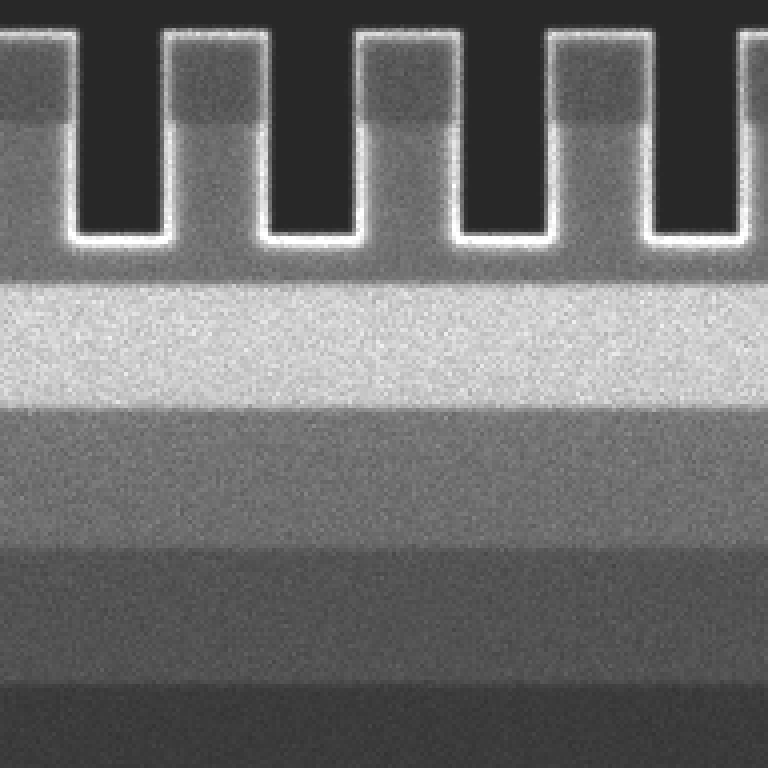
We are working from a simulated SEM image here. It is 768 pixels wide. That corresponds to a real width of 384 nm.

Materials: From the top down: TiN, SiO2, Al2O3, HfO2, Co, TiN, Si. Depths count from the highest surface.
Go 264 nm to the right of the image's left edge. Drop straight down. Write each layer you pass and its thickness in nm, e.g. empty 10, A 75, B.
empty 102, Al2O3 24, HfO2 62, Co 70, TiN 68, Si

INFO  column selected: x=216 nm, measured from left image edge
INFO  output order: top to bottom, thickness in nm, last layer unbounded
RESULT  TiN 46, SiO2 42, Al2O3 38, HfO2 62, Co 70, TiN 68, Si